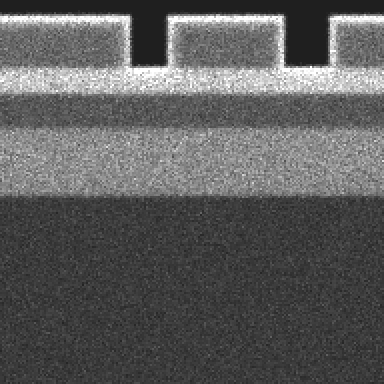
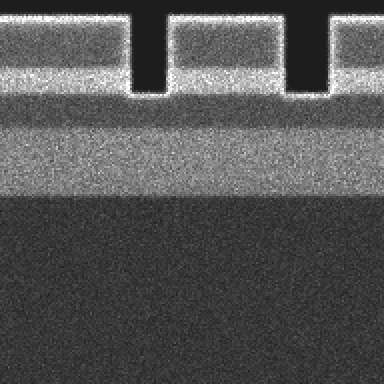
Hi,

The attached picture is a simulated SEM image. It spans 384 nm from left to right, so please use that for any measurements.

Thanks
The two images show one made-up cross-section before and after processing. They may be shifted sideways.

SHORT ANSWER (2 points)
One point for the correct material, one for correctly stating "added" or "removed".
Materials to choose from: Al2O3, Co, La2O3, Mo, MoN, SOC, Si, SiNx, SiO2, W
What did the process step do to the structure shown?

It removed W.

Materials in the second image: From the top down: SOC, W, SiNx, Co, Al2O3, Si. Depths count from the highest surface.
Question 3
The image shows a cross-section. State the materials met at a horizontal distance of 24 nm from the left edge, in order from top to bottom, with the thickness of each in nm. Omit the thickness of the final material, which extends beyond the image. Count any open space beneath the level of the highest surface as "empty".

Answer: SOC 52, W 26, SiNx 34, Co 60, Al2O3 8, Si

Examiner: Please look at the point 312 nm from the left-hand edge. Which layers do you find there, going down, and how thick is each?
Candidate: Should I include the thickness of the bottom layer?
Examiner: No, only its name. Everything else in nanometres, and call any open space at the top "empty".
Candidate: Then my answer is empty 78, SiNx 34, Co 60, Al2O3 8, Si